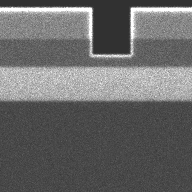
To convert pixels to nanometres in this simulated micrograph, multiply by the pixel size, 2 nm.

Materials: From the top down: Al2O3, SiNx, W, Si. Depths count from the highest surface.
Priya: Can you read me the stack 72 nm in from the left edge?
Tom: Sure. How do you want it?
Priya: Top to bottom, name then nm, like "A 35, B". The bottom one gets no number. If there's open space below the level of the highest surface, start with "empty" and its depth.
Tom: Al2O3 62, SiNx 56, W 68, Si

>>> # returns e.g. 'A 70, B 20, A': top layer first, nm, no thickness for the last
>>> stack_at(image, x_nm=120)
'Al2O3 62, SiNx 56, W 68, Si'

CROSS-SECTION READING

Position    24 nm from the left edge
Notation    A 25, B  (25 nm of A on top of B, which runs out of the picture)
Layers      Al2O3 62, SiNx 56, W 68, Si